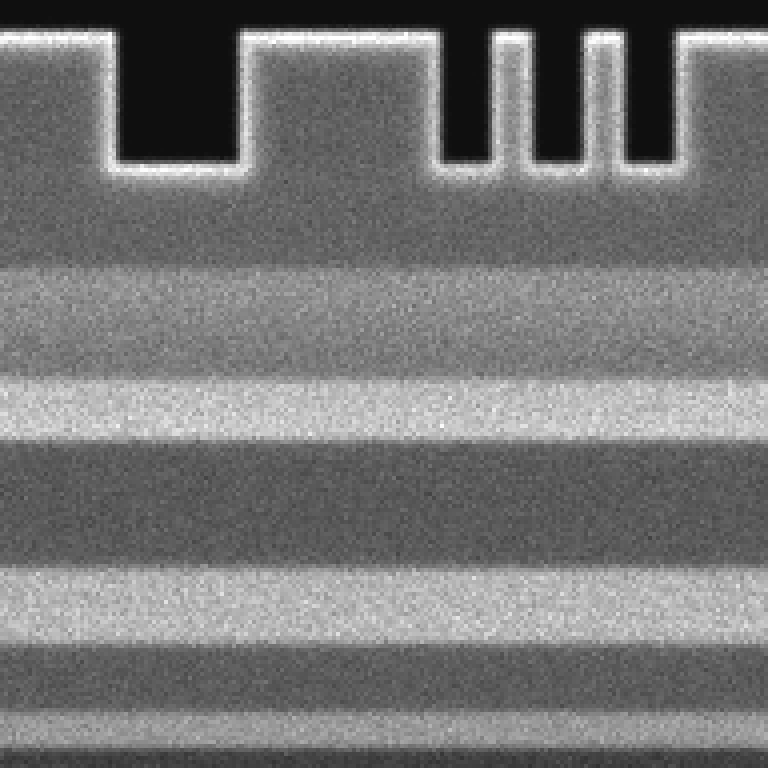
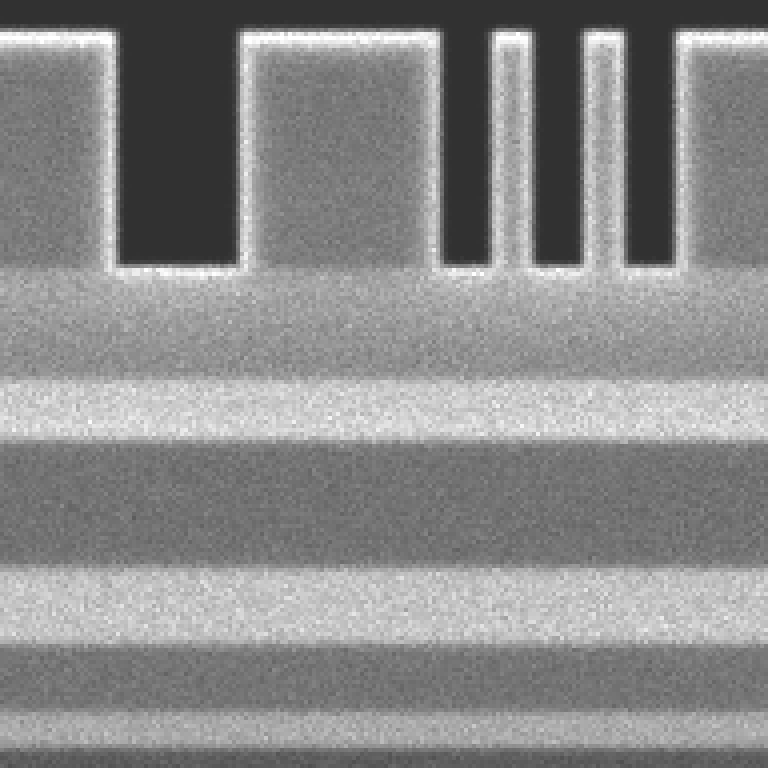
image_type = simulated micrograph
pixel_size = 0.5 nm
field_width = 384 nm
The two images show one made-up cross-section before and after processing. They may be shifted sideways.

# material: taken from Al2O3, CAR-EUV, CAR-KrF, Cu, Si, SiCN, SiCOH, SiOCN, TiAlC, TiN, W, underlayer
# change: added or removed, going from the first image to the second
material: underlayer
change: removed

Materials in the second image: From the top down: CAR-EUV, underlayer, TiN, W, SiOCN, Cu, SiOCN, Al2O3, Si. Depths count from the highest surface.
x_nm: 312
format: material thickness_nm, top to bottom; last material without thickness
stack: empty 118, TiN 56, W 30, SiOCN 64, Cu 38, SiOCN 34, Al2O3 18, Si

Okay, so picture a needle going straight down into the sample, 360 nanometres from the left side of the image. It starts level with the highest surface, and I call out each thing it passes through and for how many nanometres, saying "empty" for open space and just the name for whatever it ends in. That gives CAR-EUV 66, underlayer 52, TiN 56, W 30, SiOCN 64, Cu 38, SiOCN 34, Al2O3 18, Si